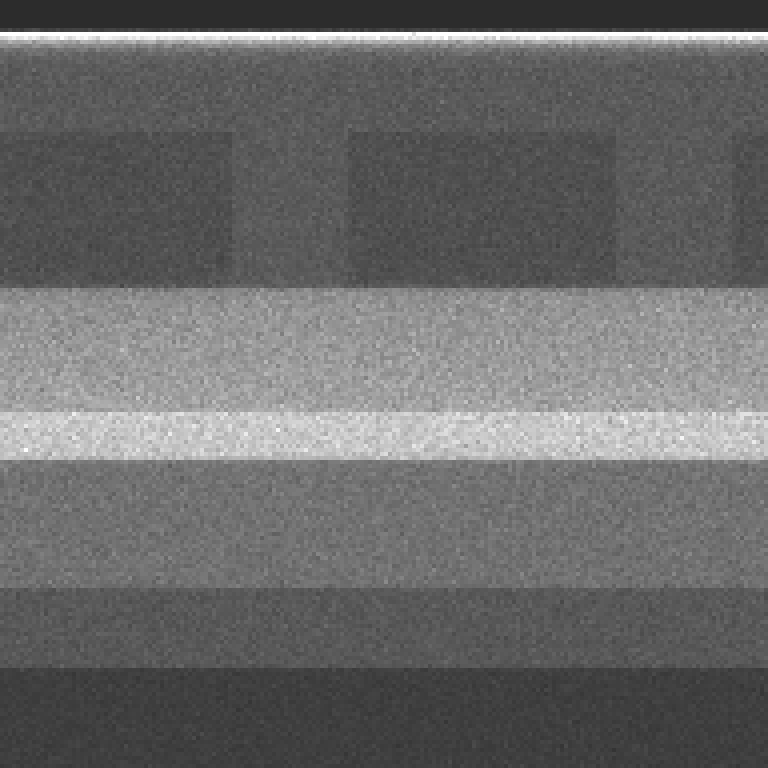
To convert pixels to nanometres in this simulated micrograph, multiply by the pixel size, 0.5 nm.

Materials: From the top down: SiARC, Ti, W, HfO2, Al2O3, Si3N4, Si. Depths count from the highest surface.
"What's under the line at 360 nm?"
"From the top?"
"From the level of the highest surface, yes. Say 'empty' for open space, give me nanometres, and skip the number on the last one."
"SiARC 128, W 62, HfO2 24, Al2O3 64, Si3N4 40, Si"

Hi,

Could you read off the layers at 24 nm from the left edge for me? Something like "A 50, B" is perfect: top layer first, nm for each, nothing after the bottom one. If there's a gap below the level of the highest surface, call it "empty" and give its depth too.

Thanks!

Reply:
SiARC 50, Ti 78, W 62, HfO2 24, Al2O3 64, Si3N4 40, Si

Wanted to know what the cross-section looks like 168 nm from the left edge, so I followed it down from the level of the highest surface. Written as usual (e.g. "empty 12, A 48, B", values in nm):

SiARC 128, W 62, HfO2 24, Al2O3 64, Si3N4 40, Si